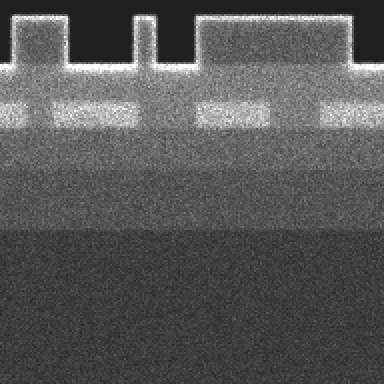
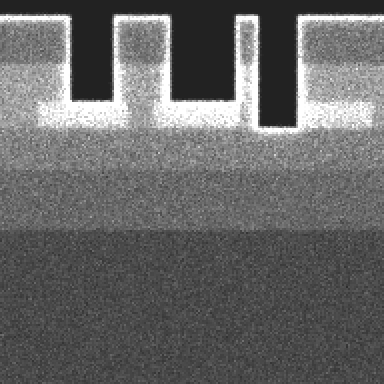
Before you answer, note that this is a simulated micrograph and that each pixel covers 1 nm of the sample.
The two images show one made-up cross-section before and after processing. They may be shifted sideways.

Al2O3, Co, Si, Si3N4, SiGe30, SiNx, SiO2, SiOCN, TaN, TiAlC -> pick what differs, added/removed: SiO2 removed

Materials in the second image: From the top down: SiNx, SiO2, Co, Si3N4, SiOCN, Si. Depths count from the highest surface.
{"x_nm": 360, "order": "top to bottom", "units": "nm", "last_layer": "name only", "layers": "SiNx 48, SiO2 38, Co 26, Si3N4 42, SiOCN 60, Si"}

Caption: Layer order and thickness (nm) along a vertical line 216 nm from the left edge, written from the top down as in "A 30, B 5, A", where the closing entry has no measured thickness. empty 86, Co 26, Si3N4 42, SiOCN 60, Si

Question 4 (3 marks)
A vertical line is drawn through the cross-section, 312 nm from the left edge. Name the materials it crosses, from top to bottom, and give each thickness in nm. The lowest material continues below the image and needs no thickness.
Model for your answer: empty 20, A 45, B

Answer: SiNx 48, SiO2 38, Co 26, Si3N4 42, SiOCN 60, Si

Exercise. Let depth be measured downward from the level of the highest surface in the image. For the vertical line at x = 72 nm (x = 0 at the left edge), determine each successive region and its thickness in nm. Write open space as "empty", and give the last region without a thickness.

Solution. empty 86, Co 26, Si3N4 42, SiOCN 60, Si